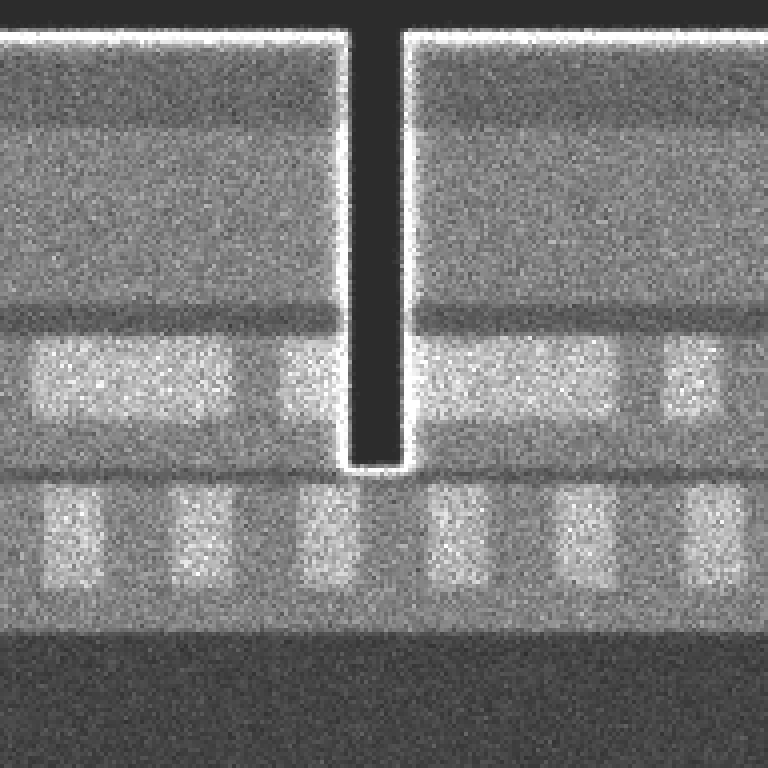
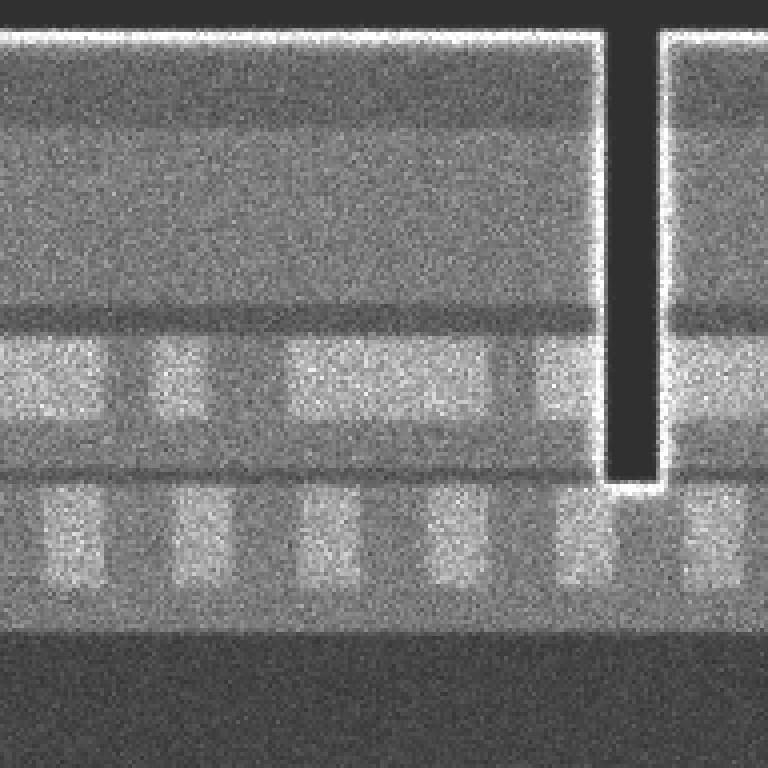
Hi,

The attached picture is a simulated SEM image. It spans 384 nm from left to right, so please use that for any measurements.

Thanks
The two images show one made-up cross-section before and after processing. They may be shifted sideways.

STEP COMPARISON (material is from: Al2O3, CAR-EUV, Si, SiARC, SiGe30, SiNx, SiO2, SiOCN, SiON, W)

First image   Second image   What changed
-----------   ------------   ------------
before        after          SiNx, removed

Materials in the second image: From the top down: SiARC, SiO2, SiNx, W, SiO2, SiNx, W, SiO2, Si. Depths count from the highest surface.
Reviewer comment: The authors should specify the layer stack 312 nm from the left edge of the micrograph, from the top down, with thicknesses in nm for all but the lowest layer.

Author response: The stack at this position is empty 226, SiO2 74, Si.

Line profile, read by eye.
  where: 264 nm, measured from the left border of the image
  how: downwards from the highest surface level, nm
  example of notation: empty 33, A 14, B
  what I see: SiARC 48, SiO2 88, SiNx 16, SiO2 66, SiNx 8, SiO2 74, Si